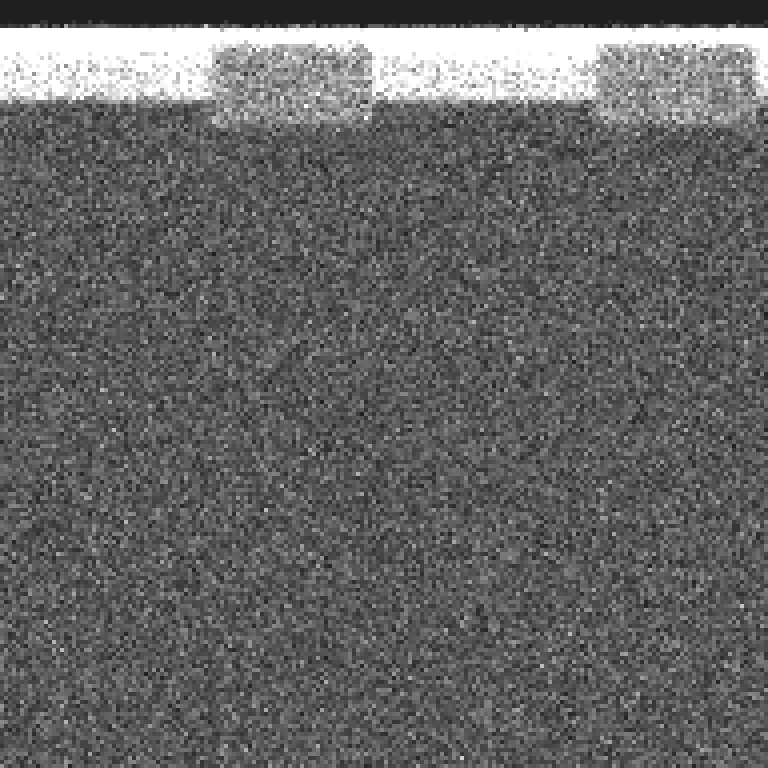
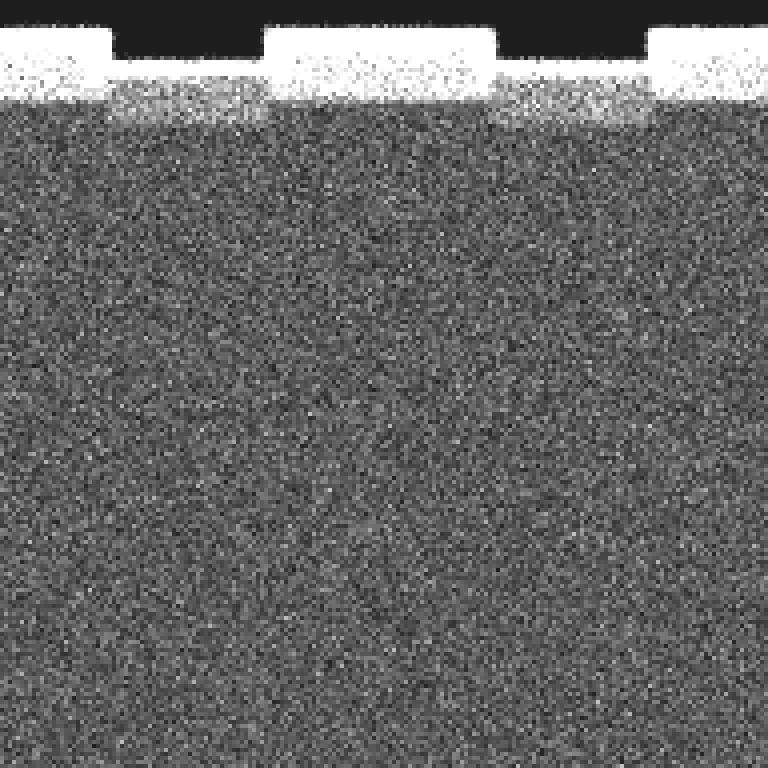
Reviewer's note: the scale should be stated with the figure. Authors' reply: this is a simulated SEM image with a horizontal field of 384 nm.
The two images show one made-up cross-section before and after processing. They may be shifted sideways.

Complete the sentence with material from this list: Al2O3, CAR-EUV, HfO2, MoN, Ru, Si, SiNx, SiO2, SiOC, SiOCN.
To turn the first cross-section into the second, SiNx must be removed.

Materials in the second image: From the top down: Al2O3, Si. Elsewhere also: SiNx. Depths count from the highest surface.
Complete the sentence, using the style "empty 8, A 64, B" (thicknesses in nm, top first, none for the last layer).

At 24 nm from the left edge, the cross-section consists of Al2O3 34, Si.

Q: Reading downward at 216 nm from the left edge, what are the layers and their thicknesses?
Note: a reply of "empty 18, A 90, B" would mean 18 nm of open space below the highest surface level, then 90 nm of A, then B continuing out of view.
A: Al2O3 34, Si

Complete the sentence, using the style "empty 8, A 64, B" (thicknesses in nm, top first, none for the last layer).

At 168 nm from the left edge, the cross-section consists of Al2O3 34, Si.